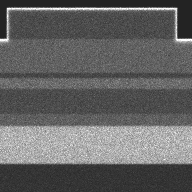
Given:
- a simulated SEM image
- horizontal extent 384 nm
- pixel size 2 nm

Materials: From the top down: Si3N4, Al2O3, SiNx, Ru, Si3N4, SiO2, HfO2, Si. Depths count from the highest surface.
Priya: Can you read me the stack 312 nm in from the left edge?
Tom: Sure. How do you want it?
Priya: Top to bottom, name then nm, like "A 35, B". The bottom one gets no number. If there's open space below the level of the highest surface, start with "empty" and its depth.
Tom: Si3N4 62, Al2O3 68, SiNx 10, Ru 22, Si3N4 50, SiO2 24, HfO2 76, Si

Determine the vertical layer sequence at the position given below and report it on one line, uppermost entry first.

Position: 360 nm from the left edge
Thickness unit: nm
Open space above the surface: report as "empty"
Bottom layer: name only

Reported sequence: empty 62, Al2O3 68, SiNx 10, Ru 22, Si3N4 50, SiO2 24, HfO2 76, Si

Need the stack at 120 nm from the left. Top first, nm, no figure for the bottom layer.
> Si3N4 62, Al2O3 68, SiNx 10, Ru 22, Si3N4 50, SiO2 24, HfO2 76, Si